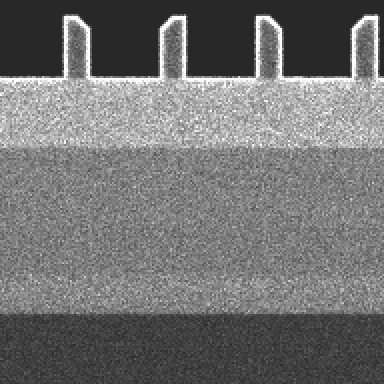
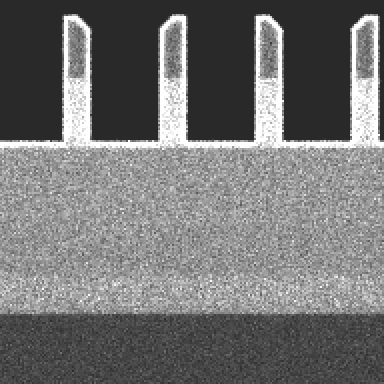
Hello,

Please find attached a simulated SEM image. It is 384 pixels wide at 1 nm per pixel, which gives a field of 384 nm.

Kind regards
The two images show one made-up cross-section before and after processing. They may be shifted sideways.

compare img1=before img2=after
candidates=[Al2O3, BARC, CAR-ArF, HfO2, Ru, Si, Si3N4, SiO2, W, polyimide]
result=removed:W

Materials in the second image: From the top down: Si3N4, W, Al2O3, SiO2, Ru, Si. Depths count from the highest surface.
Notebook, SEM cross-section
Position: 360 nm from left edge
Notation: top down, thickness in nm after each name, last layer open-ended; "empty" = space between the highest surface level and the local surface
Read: empty 4, Si3N4 58, W 70, Al2O3 78, SiO2 50, Ru 38, Si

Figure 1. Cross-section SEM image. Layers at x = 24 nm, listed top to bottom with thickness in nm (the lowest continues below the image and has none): empty 126, W 6, Al2O3 78, SiO2 50, Ru 38, Si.